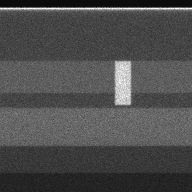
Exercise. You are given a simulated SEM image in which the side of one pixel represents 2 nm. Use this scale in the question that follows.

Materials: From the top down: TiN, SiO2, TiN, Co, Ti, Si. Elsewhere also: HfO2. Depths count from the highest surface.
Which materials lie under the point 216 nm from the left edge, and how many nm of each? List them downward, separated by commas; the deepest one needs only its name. TiN 106, SiO2 64, TiN 30, Co 76, Ti 54, Si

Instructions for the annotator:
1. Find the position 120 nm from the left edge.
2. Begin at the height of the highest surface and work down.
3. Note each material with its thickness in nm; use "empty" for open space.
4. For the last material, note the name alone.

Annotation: TiN 106, SiO2 64, TiN 30, Co 76, Ti 54, Si